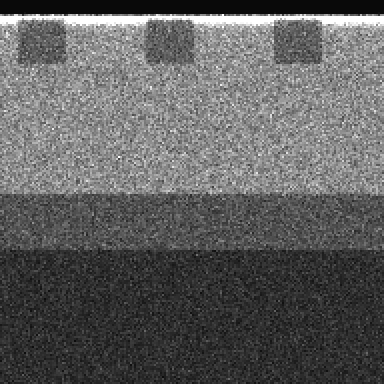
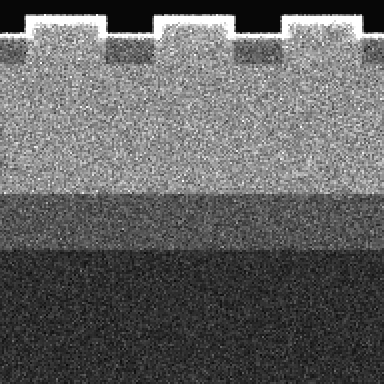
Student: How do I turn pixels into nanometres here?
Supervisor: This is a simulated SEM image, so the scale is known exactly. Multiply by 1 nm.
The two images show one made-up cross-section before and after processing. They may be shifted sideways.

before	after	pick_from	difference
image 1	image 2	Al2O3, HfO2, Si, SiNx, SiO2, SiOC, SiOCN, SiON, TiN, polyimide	TiN removed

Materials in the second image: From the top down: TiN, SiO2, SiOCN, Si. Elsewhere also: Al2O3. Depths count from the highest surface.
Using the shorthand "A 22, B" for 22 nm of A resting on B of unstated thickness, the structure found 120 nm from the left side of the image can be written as empty 18, TiN 30, SiO2 130, SiOCN 56, Si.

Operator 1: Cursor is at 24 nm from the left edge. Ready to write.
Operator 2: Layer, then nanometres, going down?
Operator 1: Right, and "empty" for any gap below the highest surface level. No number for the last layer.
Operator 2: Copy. empty 18, TiN 30, SiO2 130, SiOCN 56, Si